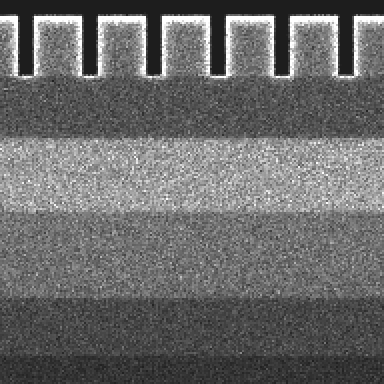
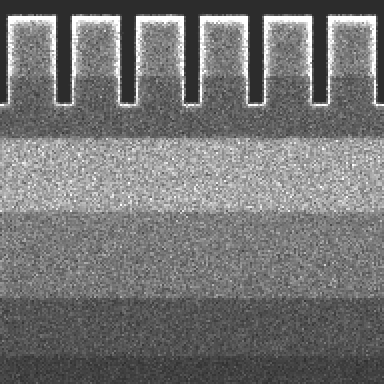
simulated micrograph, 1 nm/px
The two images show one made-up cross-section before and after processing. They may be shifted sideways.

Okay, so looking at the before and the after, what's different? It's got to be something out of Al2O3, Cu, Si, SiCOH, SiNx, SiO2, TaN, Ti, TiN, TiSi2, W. TiN, removed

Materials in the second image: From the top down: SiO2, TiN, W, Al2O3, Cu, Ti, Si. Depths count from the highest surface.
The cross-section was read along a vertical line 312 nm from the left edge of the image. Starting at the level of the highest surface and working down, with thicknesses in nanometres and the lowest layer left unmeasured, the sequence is empty 88, TiN 34, W 74, Al2O3 36, Cu 50, Ti 58, Si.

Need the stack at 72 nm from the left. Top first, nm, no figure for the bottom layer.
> SiO2 60, TiN 62, W 74, Al2O3 36, Cu 50, Ti 58, Si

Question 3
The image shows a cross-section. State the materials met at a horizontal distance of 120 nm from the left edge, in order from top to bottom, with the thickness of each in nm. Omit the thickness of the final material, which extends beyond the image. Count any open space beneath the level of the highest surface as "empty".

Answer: empty 88, TiN 34, W 74, Al2O3 36, Cu 50, Ti 58, Si